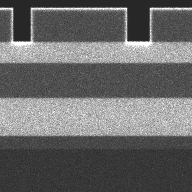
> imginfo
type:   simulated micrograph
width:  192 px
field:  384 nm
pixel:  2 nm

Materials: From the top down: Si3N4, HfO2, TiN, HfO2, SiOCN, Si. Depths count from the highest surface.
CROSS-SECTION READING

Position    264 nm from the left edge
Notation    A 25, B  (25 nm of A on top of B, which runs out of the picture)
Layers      empty 68, HfO2 42, TiN 70, HfO2 76, SiOCN 26, Si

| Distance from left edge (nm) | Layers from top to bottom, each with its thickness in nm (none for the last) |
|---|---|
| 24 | Si3N4 68, HfO2 42, TiN 70, HfO2 76, SiOCN 26, Si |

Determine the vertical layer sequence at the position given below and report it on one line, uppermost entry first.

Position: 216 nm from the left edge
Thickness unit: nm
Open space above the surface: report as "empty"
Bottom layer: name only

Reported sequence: Si3N4 68, HfO2 42, TiN 70, HfO2 76, SiOCN 26, Si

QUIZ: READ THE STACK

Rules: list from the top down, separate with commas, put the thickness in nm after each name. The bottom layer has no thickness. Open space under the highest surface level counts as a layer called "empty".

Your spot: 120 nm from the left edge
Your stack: Si3N4 68, HfO2 42, TiN 70, HfO2 76, SiOCN 26, Si